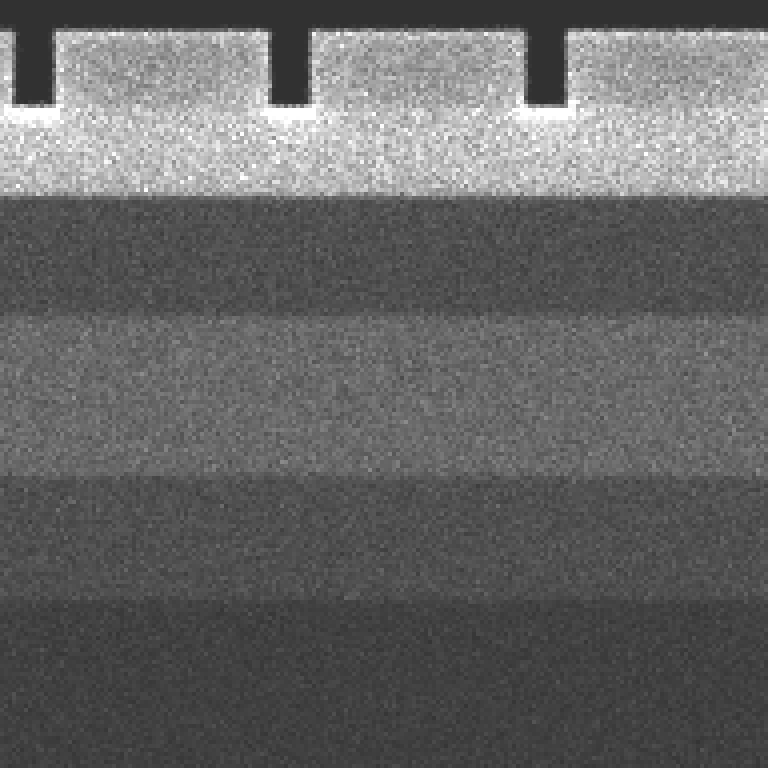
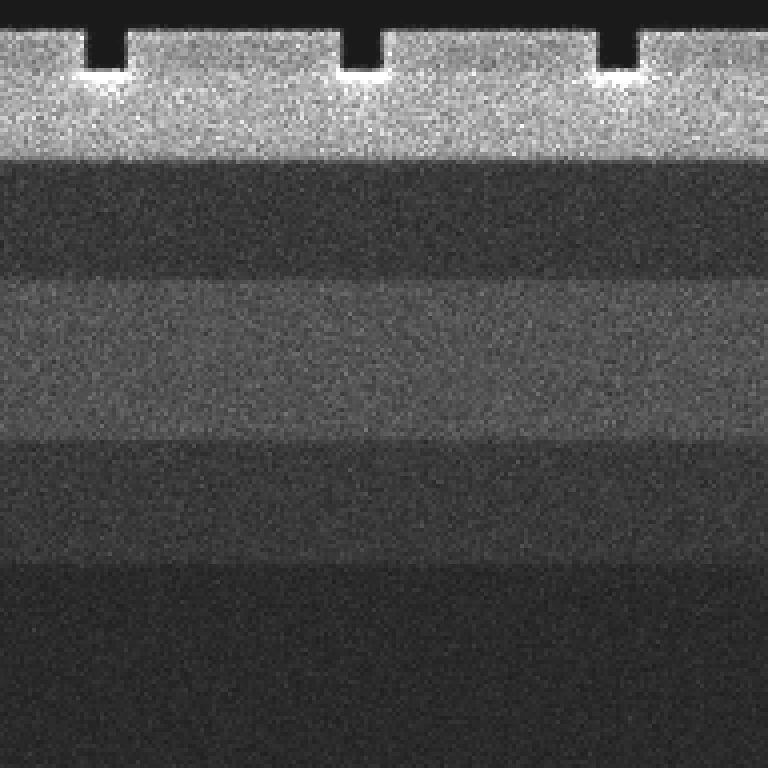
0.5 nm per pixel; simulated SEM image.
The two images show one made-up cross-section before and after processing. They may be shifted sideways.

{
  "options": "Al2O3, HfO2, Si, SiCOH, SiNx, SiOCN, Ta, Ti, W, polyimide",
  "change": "removed",
  "material": "W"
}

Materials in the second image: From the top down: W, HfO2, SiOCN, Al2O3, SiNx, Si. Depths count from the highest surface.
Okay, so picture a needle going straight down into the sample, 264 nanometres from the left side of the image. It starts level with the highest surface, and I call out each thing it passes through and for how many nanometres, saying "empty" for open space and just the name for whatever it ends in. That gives W 20, HfO2 44, SiOCN 60, Al2O3 80, SiNx 62, Si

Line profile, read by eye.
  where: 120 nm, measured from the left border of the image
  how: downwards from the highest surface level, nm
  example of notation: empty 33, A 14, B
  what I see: W 20, HfO2 44, SiOCN 60, Al2O3 80, SiNx 62, Si